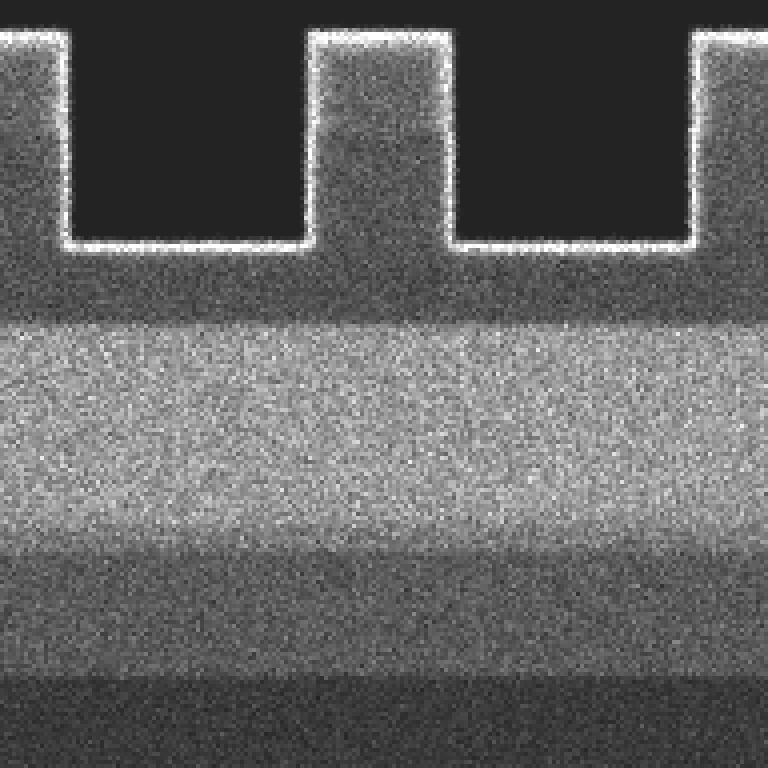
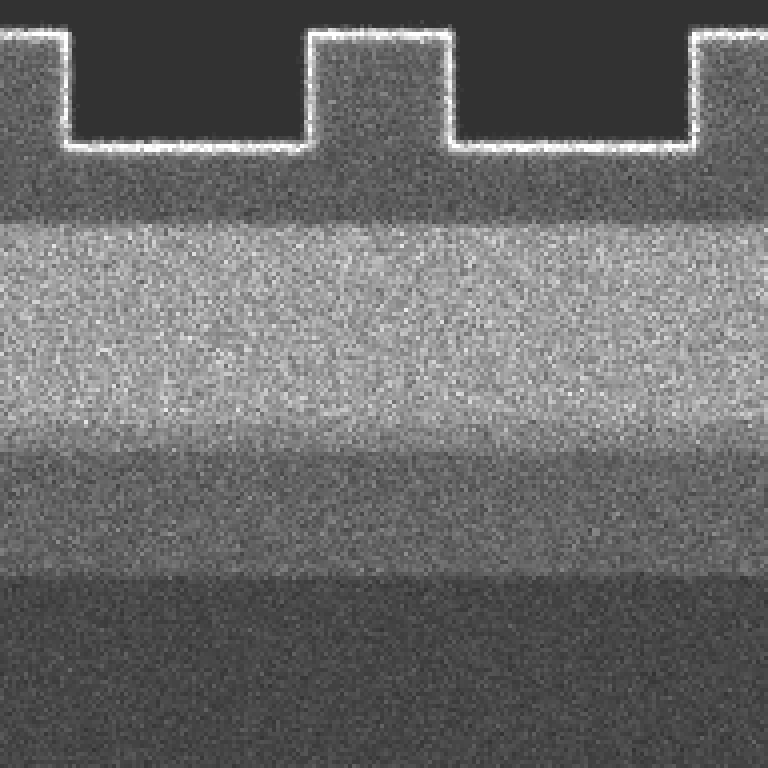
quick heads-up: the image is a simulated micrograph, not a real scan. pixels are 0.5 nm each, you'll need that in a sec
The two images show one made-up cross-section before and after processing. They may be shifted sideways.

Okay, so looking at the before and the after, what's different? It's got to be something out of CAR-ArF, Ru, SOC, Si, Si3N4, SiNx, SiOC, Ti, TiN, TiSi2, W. SOC, removed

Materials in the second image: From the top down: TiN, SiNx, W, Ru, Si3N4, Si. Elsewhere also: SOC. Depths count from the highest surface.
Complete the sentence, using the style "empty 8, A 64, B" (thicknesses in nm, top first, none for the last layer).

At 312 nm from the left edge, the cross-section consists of empty 56, SiNx 40, W 100, Ru 14, Si3N4 62, Si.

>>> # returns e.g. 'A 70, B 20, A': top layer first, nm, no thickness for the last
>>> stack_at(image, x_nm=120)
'empty 56, SiNx 40, W 100, Ru 14, Si3N4 62, Si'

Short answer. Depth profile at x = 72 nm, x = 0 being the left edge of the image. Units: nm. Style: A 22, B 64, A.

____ empty 56, SiNx 40, W 100, Ru 14, Si3N4 62, Si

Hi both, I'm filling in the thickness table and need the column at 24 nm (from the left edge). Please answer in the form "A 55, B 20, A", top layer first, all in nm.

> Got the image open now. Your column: TiN 56, SiNx 40, W 100, Ru 14, Si3N4 62, Si